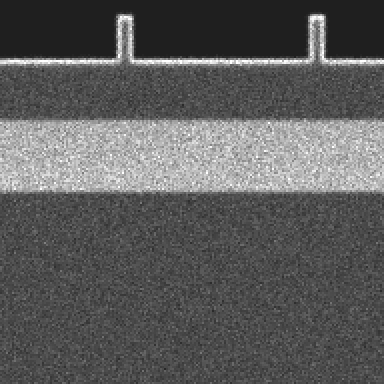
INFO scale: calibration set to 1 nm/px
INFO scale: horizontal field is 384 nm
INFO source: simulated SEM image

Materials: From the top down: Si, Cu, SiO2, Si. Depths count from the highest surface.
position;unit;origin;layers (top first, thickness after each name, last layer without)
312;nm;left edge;Si 104, Cu 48, SiO2 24, Si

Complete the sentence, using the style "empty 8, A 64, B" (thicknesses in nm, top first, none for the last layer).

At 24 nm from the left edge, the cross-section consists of empty 44, Si 60, Cu 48, SiO2 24, Si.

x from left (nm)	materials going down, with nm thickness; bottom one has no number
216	empty 44, Si 60, Cu 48, SiO2 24, Si